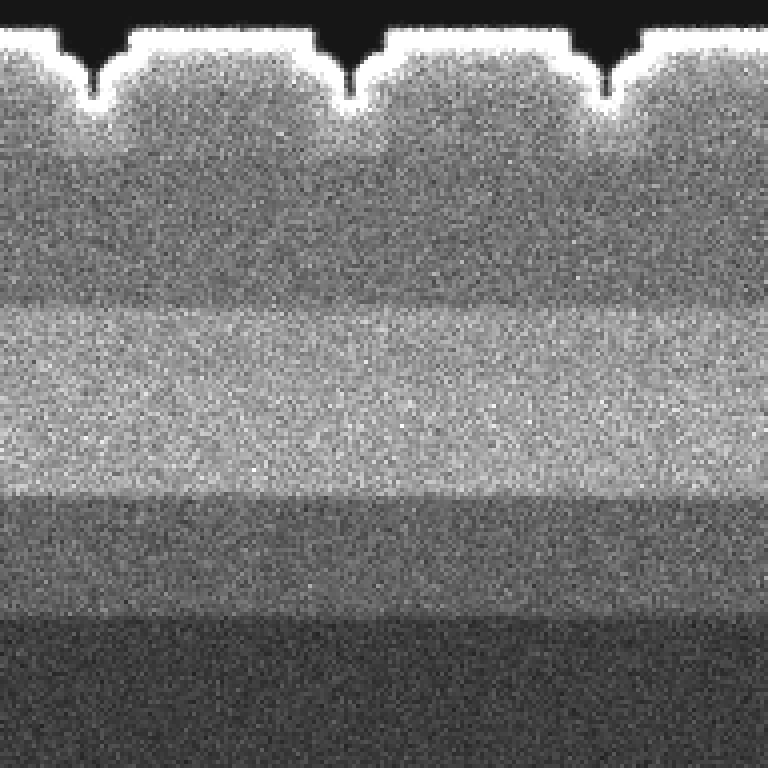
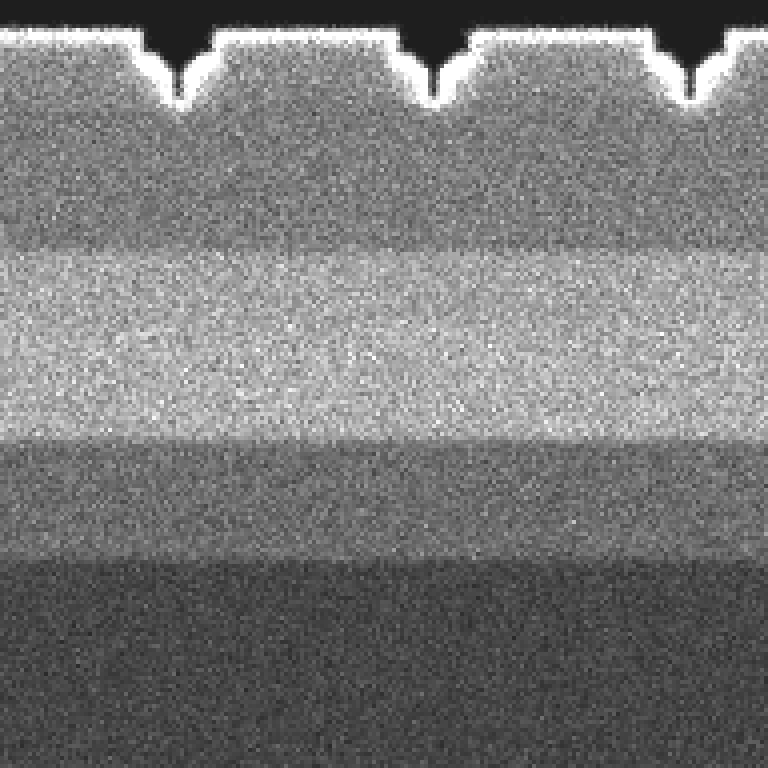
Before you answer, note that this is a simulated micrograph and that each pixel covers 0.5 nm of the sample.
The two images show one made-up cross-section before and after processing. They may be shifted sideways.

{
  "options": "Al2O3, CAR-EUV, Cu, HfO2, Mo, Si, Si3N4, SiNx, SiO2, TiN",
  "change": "removed",
  "material": "SiO2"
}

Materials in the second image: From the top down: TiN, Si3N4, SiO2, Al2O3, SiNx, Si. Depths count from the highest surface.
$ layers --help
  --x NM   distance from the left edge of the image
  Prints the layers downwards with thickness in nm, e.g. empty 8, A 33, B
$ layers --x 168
TiN 34, Si3N4 76, SiO2 36, Al2O3 58, SiNx 60, Si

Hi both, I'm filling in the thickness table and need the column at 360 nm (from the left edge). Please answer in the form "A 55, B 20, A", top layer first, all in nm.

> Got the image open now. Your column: empty 12, SiO2 22, Si3N4 76, SiO2 36, Al2O3 58, SiNx 60, Si